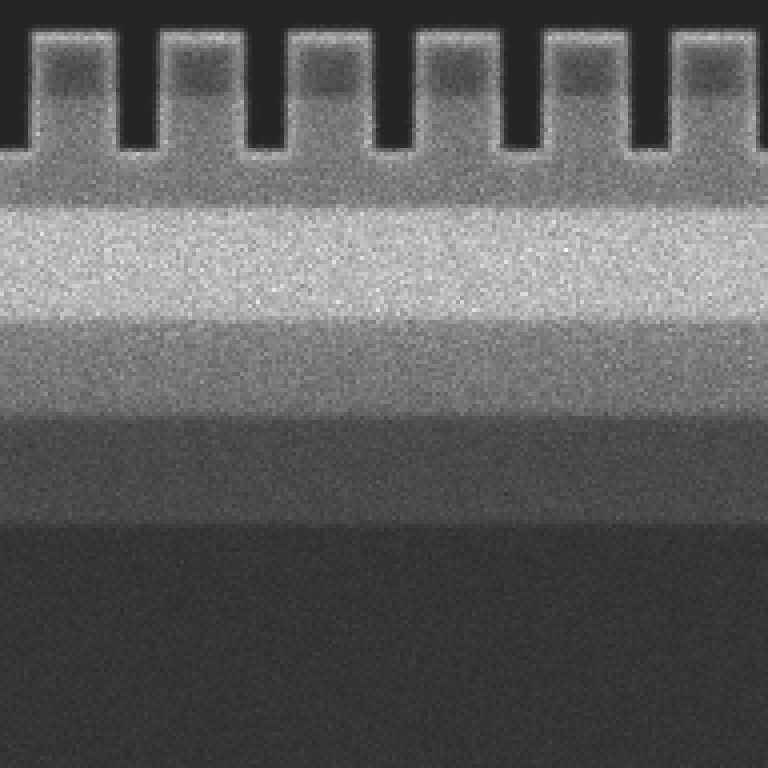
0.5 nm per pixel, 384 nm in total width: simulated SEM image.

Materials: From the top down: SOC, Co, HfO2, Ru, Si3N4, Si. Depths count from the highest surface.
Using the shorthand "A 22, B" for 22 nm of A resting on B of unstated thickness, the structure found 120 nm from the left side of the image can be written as SOC 32, Co 56, HfO2 56, Ru 48, Si3N4 54, Si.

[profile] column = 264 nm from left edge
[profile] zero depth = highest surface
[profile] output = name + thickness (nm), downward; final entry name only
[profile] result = empty 60, Co 28, HfO2 56, Ru 48, Si3N4 54, Si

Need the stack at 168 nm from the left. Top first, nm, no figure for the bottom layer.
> SOC 32, Co 56, HfO2 56, Ru 48, Si3N4 54, Si